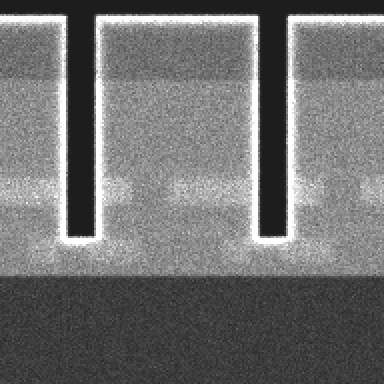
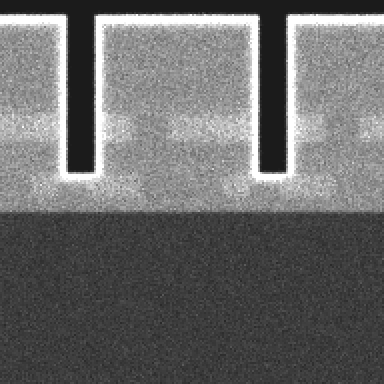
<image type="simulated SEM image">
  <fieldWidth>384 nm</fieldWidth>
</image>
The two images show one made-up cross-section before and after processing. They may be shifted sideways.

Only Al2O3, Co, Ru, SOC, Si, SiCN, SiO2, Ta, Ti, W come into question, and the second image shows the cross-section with SOC removed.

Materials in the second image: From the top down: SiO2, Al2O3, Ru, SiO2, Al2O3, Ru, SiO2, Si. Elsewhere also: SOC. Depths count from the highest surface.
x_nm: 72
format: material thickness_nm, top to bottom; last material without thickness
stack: empty 158, SiO2 38, Si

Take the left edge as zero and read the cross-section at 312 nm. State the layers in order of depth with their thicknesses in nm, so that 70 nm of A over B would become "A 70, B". SiO2 86, Al2O3 12, Ru 28, SiO2 18, Al2O3 14, Ru 24, SiO2 14, Si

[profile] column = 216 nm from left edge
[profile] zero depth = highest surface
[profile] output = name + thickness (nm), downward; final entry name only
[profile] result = SiO2 86, Al2O3 12, Ru 28, SiO2 18, Al2O3 14, SiO2 38, Si